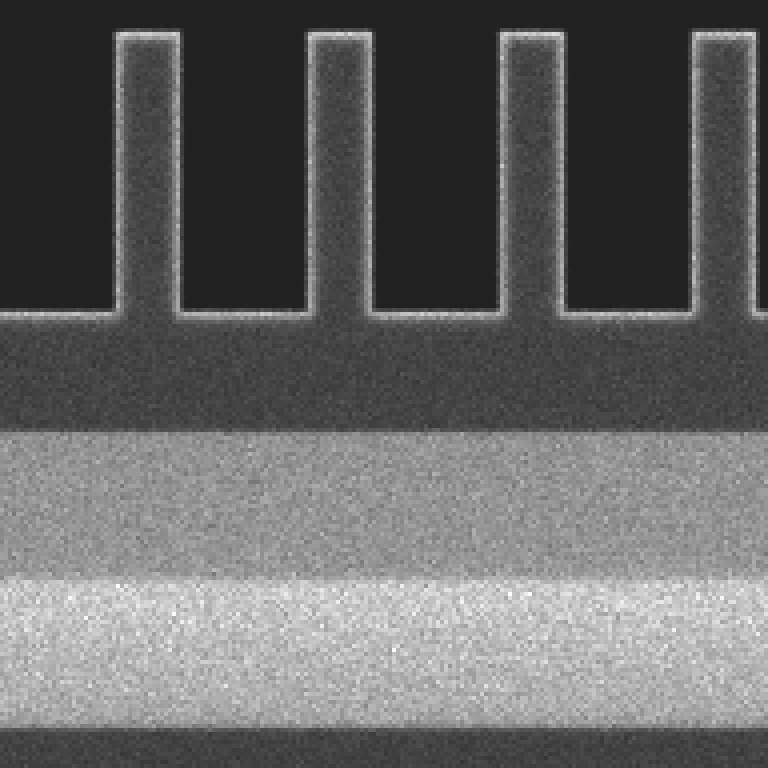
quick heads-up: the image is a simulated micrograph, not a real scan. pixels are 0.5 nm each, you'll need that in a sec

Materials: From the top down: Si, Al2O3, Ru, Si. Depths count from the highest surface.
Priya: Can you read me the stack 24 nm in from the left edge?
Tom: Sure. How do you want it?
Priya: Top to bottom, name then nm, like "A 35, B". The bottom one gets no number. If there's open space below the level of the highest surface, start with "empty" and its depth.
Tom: empty 140, Si 60, Al2O3 74, Ru 74, Si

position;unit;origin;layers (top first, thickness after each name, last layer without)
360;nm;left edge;Si 200, Al2O3 74, Ru 74, Si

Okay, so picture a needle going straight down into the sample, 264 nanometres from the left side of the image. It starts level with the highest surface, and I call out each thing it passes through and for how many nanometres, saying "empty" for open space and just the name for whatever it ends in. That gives Si 200, Al2O3 74, Ru 74, Si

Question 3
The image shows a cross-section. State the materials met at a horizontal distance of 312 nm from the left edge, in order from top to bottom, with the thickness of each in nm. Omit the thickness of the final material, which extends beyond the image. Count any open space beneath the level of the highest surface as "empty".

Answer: empty 140, Si 60, Al2O3 74, Ru 74, Si